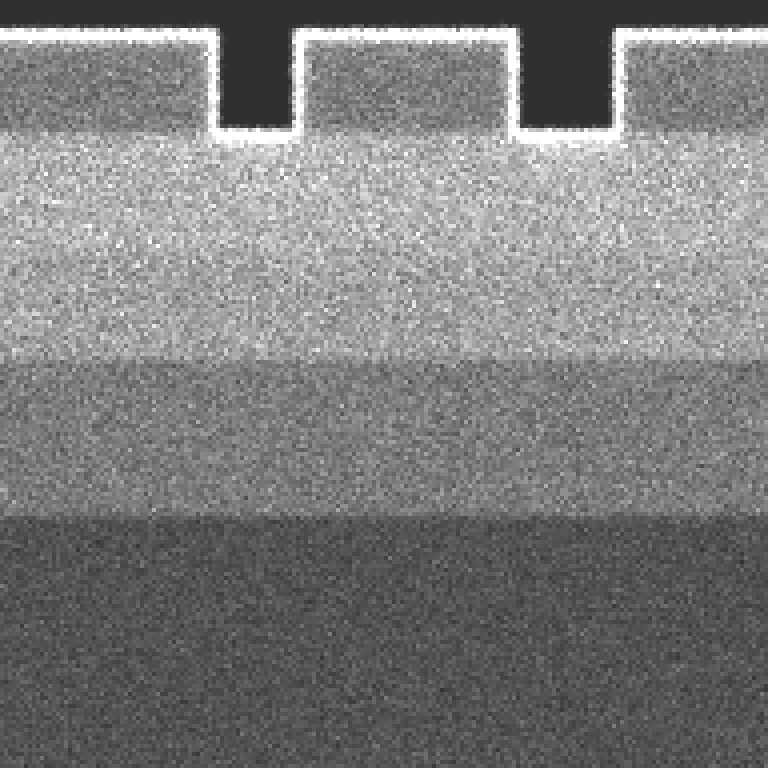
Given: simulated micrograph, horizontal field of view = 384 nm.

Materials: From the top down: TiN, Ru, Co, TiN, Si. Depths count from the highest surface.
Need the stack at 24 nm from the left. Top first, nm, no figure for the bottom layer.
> TiN 50, Ru 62, Co 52, TiN 78, Si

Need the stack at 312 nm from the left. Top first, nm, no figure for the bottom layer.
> TiN 50, Ru 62, Co 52, TiN 78, Si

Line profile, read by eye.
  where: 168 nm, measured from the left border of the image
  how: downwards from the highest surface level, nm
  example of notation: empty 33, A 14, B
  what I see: TiN 50, Ru 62, Co 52, TiN 78, Si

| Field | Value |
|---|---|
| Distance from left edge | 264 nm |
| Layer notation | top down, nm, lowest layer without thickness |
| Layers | empty 50, Ru 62, Co 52, TiN 78, Si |